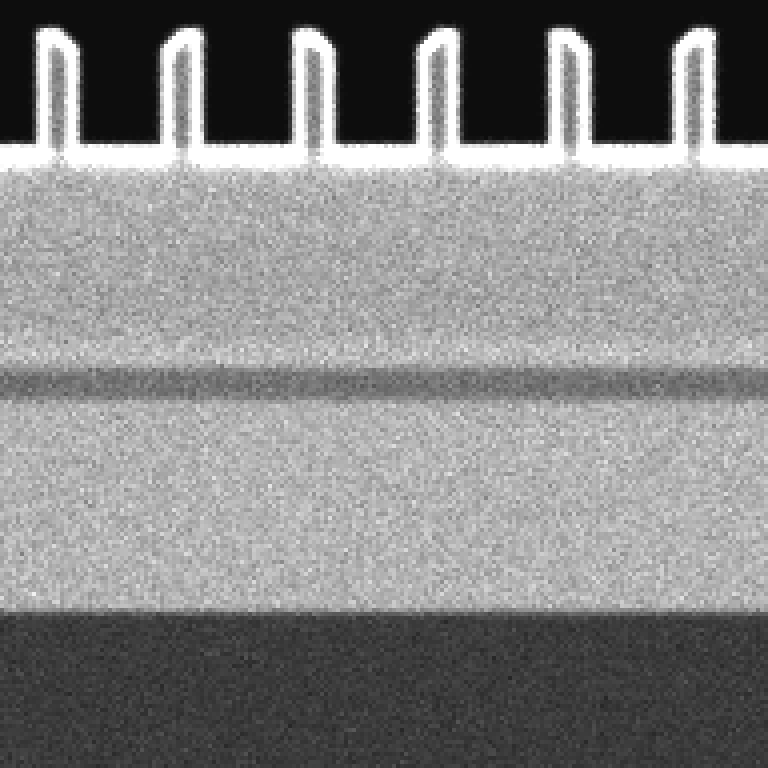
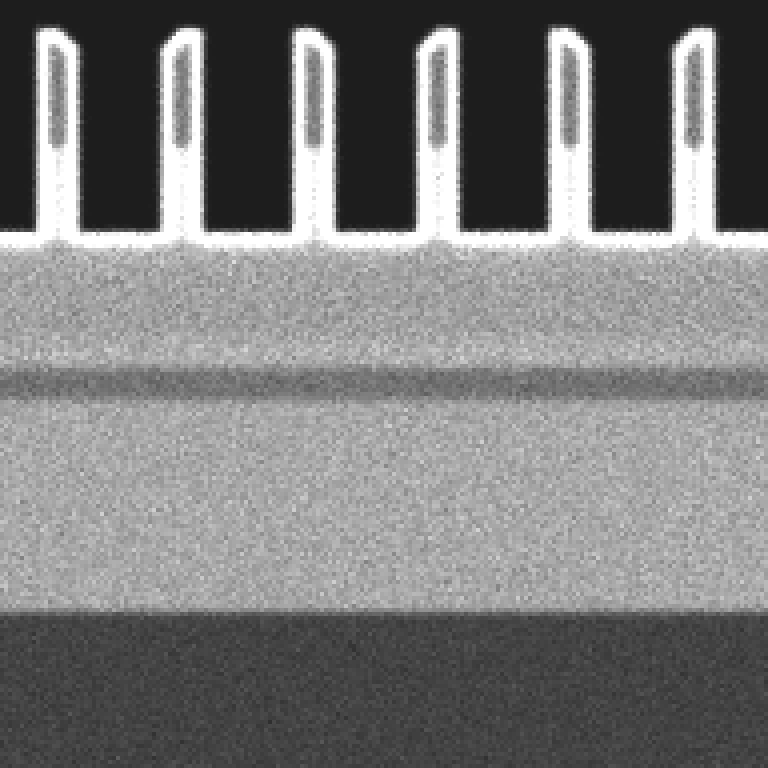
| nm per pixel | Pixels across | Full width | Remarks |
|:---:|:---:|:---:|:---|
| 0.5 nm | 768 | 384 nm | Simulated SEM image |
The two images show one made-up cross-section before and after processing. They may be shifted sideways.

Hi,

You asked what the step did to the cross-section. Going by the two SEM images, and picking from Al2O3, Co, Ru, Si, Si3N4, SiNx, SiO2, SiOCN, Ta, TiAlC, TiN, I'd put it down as SiO2, removed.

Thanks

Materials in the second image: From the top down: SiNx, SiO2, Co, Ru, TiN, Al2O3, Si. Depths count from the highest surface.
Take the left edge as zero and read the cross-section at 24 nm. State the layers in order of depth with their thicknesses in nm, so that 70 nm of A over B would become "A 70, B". SiNx 58, SiO2 44, Co 52, Ru 14, TiN 16, Al2O3 106, Si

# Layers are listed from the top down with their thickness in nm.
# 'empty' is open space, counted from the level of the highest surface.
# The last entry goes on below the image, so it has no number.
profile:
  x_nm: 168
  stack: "empty 102, Co 52, Ru 14, TiN 16, Al2O3 106, Si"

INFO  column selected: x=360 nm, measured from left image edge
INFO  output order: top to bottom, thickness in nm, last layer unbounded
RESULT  empty 102, Co 52, Ru 14, TiN 16, Al2O3 106, Si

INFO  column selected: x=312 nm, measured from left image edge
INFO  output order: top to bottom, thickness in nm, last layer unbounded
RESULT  empty 102, Co 52, Ru 14, TiN 16, Al2O3 106, Si